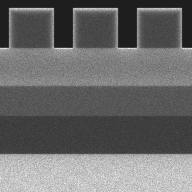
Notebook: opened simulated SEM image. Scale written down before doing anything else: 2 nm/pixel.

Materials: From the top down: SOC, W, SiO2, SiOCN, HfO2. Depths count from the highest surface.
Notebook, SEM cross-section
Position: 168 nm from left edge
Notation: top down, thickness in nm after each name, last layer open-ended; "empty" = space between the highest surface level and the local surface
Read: SOC 80, W 76, SiO2 60, SiOCN 76, HfO2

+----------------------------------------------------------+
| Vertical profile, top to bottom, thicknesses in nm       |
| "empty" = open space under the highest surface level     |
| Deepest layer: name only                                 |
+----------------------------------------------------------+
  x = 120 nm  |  empty 80, W 76, SiO2 60, SiOCN 76, HfO2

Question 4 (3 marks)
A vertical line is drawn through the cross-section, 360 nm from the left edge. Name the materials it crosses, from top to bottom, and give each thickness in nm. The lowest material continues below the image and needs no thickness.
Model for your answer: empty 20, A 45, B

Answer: SOC 80, W 76, SiO2 60, SiOCN 76, HfO2